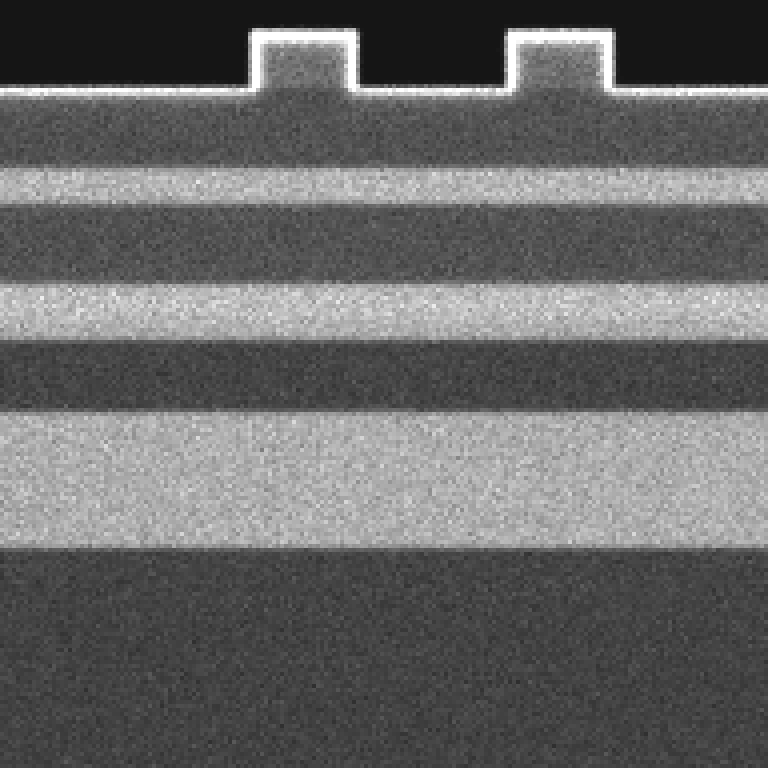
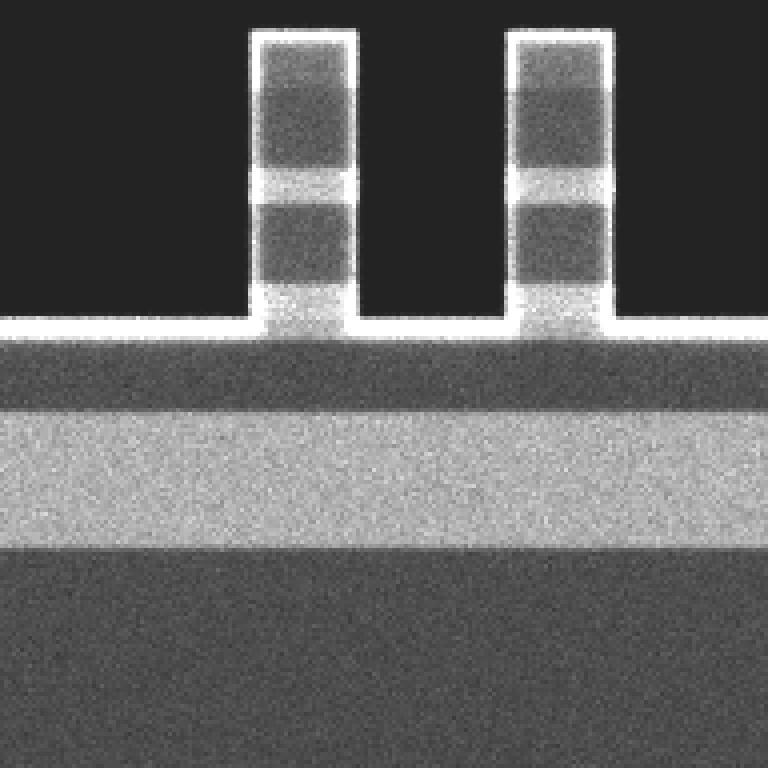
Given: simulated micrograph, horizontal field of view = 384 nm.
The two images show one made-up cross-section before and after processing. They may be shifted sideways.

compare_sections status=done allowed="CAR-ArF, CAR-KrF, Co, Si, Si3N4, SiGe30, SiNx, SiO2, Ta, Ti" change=removed material="Co and SiGe30"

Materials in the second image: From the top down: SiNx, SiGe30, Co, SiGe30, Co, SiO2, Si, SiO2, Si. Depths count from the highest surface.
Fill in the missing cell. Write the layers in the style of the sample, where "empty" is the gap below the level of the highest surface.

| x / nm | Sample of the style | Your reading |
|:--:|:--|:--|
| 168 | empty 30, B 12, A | SiNx 28, SiGe30 40, Co 18, SiGe30 40, Co 18, SiO2 10, Si 36, SiO2 68, Si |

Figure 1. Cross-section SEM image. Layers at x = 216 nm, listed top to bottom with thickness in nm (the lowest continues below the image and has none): empty 144, SiO2 10, Si 36, SiO2 68, Si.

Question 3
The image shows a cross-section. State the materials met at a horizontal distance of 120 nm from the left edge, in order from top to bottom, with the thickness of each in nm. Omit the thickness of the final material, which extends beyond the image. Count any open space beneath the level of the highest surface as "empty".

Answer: empty 144, SiO2 10, Si 36, SiO2 68, Si